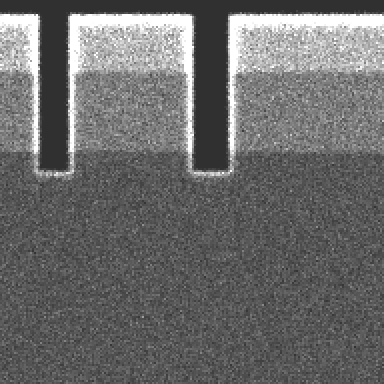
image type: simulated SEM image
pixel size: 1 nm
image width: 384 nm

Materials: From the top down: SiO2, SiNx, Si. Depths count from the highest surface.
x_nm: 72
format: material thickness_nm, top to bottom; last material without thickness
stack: SiO2 56, SiNx 80, Si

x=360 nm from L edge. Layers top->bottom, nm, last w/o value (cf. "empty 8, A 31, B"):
SiO2 56, SiNx 80, Si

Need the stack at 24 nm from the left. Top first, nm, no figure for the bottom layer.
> SiO2 56, SiNx 80, Si